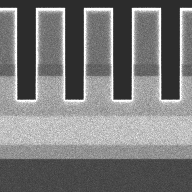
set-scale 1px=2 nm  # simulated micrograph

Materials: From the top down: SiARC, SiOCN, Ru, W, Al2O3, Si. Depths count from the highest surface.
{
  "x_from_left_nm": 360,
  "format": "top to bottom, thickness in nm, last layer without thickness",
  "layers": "SiARC 112, SiOCN 24, Ru 80, W 58, Al2O3 28, Si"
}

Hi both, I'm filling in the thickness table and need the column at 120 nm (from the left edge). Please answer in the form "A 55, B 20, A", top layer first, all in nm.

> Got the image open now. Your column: SiARC 112, SiOCN 24, Ru 80, W 58, Al2O3 28, Si